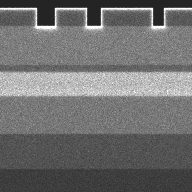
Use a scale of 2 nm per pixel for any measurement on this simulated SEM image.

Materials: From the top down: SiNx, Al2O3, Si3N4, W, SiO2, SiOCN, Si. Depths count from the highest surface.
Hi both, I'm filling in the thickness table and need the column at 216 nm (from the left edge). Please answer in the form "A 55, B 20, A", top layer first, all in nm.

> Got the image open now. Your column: SiNx 36, Al2O3 78, Si3N4 14, W 48, SiO2 76, SiOCN 70, Si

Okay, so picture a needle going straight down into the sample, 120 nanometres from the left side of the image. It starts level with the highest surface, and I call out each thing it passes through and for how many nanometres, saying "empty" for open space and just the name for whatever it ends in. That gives SiNx 36, Al2O3 78, Si3N4 14, W 48, SiO2 76, SiOCN 70, Si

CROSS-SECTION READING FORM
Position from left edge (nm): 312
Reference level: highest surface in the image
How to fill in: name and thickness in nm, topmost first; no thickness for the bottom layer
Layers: empty 36, Al2O3 78, Si3N4 14, W 48, SiO2 76, SiOCN 70, Si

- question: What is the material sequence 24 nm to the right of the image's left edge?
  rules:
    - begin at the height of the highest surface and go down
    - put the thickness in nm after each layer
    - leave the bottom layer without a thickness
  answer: SiNx 36, Al2O3 78, Si3N4 14, W 48, SiO2 76, SiOCN 70, Si